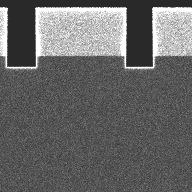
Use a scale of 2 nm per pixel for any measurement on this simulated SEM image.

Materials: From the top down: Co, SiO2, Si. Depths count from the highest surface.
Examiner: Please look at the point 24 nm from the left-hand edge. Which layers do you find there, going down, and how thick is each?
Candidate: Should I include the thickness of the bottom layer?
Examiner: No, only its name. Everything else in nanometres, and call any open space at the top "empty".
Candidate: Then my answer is empty 118, Si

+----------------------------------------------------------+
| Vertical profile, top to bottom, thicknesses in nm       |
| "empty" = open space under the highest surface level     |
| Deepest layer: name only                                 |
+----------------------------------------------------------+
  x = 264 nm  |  empty 118, Si